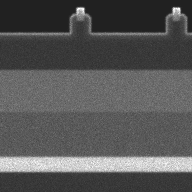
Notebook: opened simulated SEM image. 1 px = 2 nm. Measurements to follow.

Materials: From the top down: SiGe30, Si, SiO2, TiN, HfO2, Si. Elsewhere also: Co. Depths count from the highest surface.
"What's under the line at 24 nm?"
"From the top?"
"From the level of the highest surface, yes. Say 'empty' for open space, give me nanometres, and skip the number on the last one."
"empty 50, SiGe30 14, Si 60, SiO2 84, TiN 90, HfO2 30, Si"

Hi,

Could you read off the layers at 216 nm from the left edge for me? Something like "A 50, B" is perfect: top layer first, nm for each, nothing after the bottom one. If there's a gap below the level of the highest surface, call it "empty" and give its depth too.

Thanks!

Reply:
empty 50, SiGe30 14, Si 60, SiO2 84, TiN 90, HfO2 30, Si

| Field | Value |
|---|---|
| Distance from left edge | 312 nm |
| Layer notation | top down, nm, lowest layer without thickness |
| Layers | empty 50, SiGe30 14, Si 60, SiO2 84, TiN 90, HfO2 30, Si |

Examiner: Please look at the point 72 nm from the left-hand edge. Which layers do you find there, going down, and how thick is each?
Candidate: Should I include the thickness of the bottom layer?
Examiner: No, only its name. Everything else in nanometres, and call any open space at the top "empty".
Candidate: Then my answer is empty 50, SiGe30 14, Si 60, SiO2 84, TiN 90, HfO2 30, Si